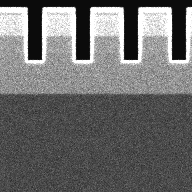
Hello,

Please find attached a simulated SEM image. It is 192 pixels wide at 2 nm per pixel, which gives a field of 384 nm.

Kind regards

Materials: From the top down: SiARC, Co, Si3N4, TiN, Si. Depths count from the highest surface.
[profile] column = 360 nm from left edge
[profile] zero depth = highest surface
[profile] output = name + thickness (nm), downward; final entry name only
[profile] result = empty 106, TiN 66, Si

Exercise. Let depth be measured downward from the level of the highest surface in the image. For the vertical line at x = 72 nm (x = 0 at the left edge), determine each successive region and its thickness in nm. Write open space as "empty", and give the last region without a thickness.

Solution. empty 106, TiN 66, Si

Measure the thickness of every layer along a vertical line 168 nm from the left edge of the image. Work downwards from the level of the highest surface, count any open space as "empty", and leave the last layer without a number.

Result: empty 106, TiN 66, Si